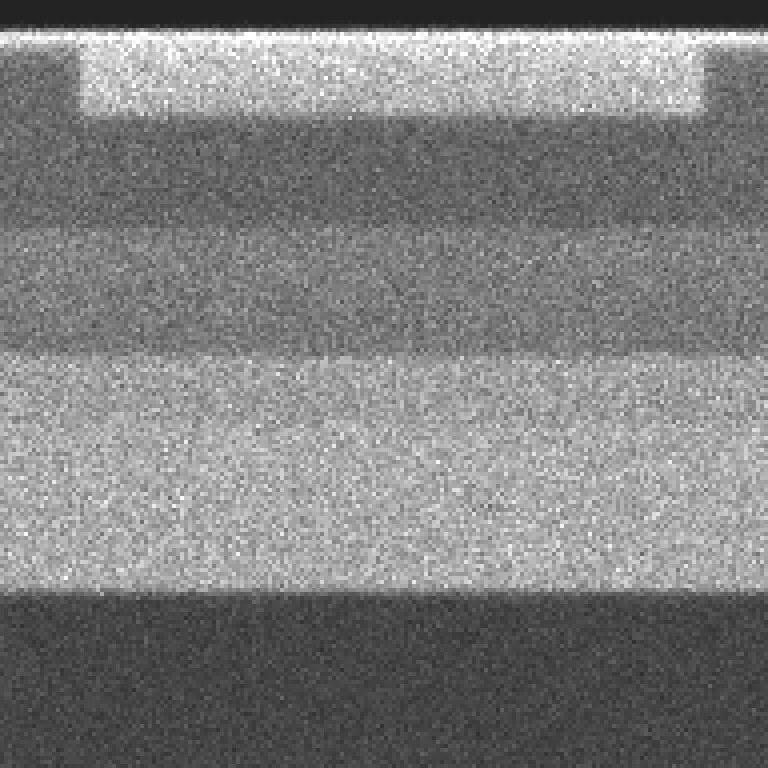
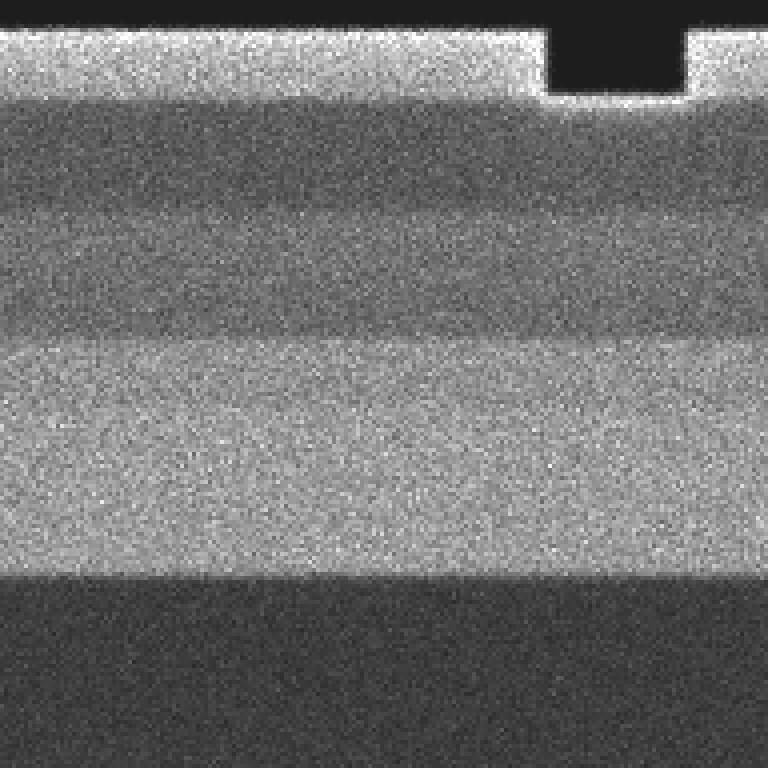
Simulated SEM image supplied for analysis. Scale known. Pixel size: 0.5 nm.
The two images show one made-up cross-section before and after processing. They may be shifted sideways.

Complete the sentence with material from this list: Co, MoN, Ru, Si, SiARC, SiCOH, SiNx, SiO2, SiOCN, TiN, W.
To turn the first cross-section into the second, SiARC must be removed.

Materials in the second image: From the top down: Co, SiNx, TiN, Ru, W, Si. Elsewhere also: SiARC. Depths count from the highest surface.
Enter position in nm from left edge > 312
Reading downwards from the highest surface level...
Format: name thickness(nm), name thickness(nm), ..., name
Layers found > empty 32, SiARC 42, SiNx 16, TiN 64, Ru 34, W 84, Si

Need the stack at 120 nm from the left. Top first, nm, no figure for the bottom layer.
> Co 34, SiNx 56, TiN 64, Ru 34, W 84, Si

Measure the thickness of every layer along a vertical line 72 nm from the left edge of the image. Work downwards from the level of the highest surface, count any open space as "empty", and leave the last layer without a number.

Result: Co 34, SiNx 56, TiN 64, Ru 34, W 84, Si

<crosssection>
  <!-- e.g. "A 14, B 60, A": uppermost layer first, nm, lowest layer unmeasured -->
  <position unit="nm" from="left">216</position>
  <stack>Co 34, SiNx 56, TiN 64, Ru 34, W 84, Si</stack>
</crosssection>